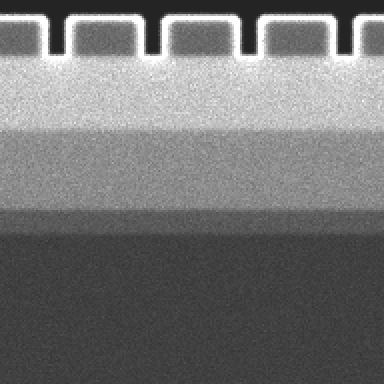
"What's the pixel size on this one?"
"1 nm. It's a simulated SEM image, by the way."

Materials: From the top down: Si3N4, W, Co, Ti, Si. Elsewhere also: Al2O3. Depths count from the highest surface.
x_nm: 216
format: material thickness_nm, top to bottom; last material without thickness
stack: Si3N4 40, W 74, Co 80, Ti 24, Si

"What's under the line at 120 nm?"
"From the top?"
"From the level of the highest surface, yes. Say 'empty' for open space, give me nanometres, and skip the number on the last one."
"Si3N4 40, W 74, Co 80, Ti 24, Si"